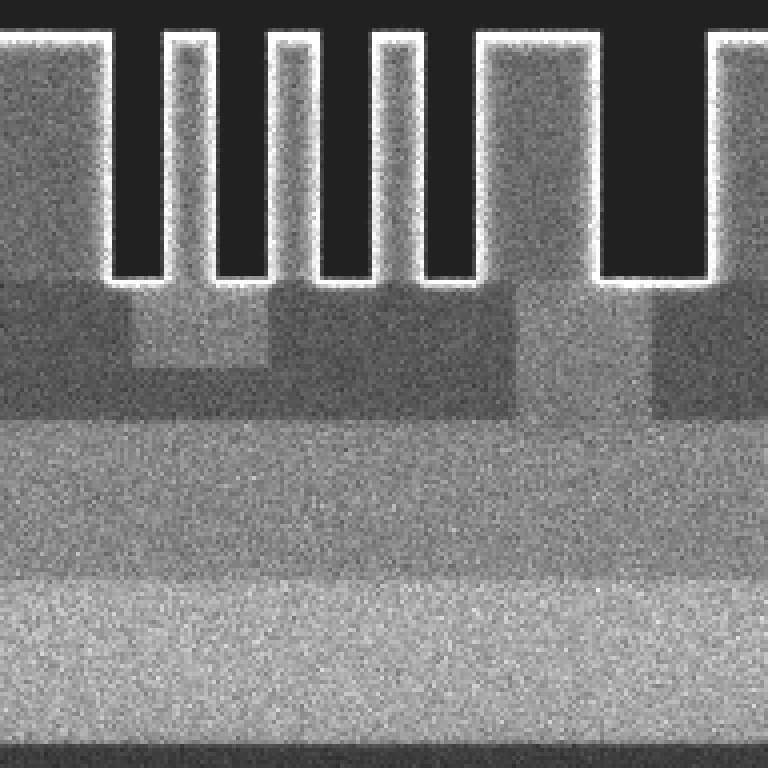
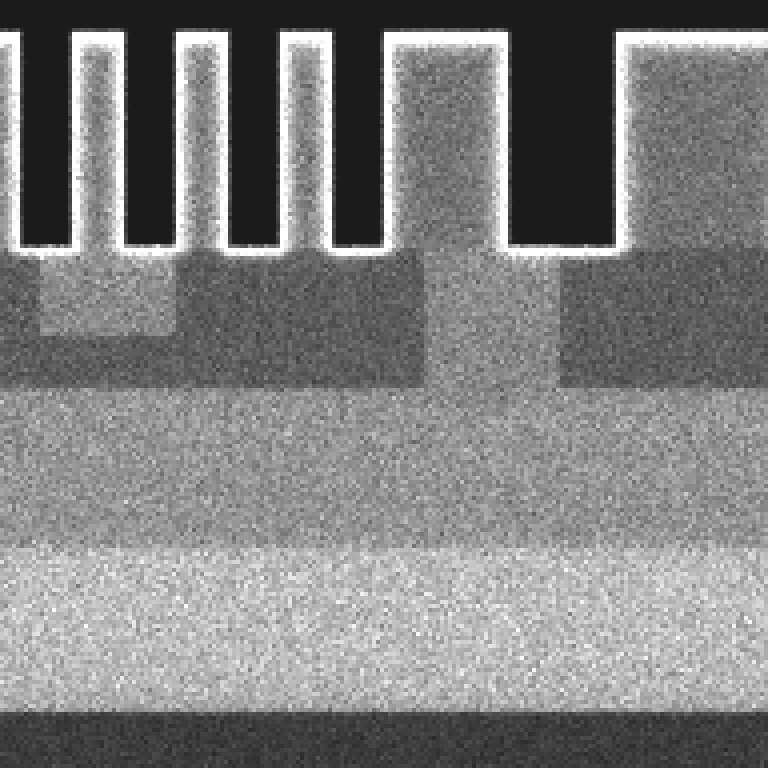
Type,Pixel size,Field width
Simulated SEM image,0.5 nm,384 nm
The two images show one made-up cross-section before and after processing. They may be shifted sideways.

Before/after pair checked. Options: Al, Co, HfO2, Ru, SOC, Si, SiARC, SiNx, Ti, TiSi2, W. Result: removed SiARC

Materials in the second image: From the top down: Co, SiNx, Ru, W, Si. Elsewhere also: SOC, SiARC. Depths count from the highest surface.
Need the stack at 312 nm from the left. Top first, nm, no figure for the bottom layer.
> SOC 108, SiNx 70, Ru 80, W 82, Si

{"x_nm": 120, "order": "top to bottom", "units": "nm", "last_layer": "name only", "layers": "empty 108, SiNx 70, Ru 80, W 82, Si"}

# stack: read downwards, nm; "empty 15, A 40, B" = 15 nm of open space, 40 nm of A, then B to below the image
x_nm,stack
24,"empty 108, Co 44, SiNx 26, Ru 80, W 82, Si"